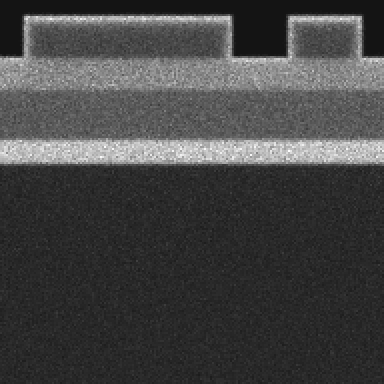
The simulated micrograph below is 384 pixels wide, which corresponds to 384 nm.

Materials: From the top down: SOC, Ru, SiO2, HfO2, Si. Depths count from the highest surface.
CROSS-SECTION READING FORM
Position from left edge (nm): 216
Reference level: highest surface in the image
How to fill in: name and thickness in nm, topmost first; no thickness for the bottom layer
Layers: SOC 42, Ru 32, SiO2 50, HfO2 24, Si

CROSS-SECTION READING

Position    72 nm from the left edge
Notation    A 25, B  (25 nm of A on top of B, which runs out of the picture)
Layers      SOC 42, Ru 32, SiO2 50, HfO2 24, Si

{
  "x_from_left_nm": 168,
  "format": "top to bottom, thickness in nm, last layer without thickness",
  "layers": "SOC 42, Ru 32, SiO2 50, HfO2 24, Si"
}